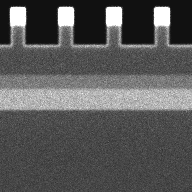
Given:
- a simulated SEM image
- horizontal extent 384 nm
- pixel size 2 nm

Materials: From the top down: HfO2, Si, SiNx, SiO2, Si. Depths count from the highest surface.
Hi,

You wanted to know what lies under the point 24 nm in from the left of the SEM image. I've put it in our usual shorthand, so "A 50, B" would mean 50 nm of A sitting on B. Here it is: HfO2 34, Si 100, SiNx 28, SiO2 42, Si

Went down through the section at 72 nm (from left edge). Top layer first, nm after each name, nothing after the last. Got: empty 74, Si 60, SiNx 28, SiO2 42, Si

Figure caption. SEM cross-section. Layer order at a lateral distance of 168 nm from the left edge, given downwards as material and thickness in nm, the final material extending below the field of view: empty 74, Si 60, SiNx 28, SiO2 42, Si